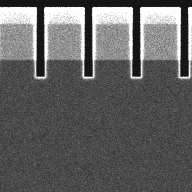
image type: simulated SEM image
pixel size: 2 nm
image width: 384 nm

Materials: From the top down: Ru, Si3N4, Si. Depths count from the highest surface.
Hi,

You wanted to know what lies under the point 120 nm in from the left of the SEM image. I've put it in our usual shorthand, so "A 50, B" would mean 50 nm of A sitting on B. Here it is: Ru 32, Si3N4 72, Si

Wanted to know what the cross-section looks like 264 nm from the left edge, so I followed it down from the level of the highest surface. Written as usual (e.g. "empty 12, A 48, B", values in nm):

empty 138, Si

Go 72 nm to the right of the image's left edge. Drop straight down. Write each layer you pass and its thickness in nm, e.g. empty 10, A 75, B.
empty 138, Si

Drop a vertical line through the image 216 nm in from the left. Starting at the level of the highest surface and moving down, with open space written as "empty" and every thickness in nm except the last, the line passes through Ru 32, Si3N4 72, Si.